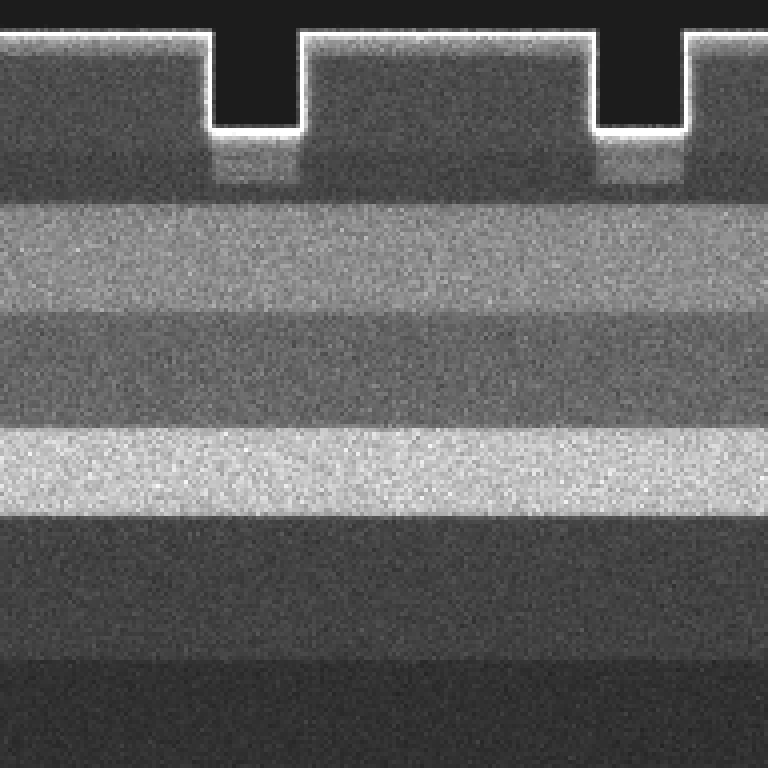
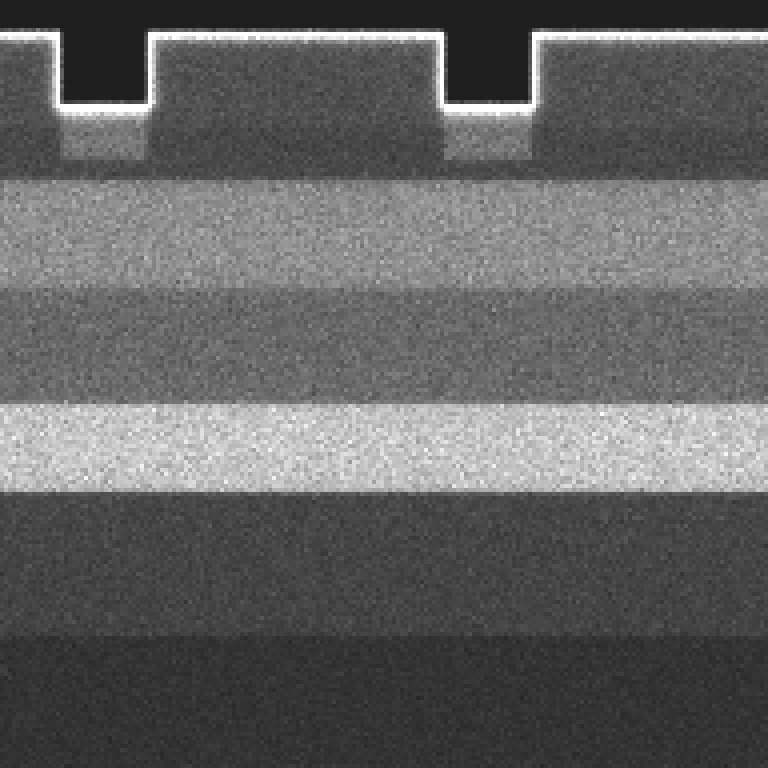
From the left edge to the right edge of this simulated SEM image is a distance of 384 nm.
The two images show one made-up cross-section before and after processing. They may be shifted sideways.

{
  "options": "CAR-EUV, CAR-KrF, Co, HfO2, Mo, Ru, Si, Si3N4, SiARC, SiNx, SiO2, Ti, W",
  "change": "removed",
  "material": "Ru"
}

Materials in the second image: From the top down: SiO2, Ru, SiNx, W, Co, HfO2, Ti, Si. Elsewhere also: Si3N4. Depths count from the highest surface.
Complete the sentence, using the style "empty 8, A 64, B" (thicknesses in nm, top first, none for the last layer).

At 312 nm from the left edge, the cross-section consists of Si3N4 48, SiNx 26, W 54, Co 58, HfO2 44, Ti 72, Si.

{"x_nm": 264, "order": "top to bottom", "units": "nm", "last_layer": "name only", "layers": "empty 36, SiO2 16, Ru 12, SiNx 10, W 54, Co 58, HfO2 44, Ti 72, Si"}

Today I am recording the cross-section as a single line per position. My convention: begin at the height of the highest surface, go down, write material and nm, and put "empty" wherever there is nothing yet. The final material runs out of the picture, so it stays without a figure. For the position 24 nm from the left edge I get Si3N4 48, SiNx 26, W 54, Co 58, HfO2 44, Ti 72, Si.